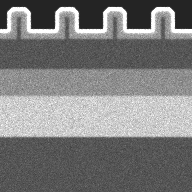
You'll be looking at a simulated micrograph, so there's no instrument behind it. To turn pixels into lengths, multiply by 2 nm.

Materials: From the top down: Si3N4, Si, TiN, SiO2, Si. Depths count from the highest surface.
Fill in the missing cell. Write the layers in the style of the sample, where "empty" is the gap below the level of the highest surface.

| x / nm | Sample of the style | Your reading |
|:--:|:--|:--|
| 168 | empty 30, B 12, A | empty 44, Si3N4 18, Si 60, TiN 54, SiO2 82, Si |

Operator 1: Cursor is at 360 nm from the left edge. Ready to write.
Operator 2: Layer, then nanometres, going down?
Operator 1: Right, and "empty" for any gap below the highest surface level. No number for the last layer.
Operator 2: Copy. empty 44, Si3N4 18, Si 60, TiN 54, SiO2 82, Si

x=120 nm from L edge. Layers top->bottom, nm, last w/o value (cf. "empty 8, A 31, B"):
Si3N4 62, Si 60, TiN 54, SiO2 82, Si